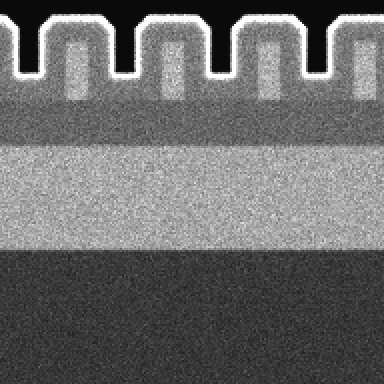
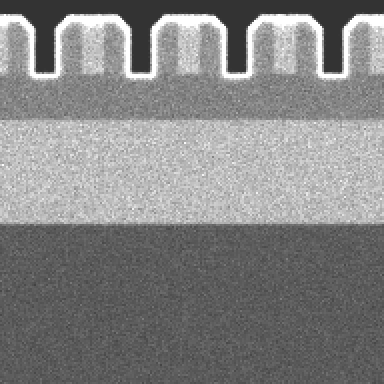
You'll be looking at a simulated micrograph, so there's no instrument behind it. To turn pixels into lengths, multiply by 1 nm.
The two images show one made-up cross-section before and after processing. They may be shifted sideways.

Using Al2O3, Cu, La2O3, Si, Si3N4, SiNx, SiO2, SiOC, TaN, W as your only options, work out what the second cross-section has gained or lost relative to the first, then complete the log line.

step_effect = removed Si3N4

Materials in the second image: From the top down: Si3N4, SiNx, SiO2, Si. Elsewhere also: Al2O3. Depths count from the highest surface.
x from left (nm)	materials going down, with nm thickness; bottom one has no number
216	empty 4, Si3N4 54, SiNx 46, SiO2 104, Si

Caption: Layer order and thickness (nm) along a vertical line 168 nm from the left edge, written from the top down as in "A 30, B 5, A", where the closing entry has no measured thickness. Si3N4 58, SiNx 46, SiO2 104, Si